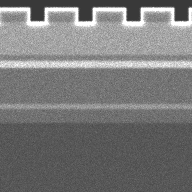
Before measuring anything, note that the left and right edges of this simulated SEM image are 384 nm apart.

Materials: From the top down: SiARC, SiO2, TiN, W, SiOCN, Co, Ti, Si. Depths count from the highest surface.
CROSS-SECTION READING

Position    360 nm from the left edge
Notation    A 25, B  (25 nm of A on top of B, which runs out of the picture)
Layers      empty 28, SiO2 66, TiN 12, W 14, SiOCN 72, Co 10, Ti 28, Si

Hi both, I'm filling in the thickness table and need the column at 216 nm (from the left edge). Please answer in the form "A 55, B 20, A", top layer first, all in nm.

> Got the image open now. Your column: SiARC 28, SiO2 66, TiN 12, W 14, SiOCN 72, Co 10, Ti 28, Si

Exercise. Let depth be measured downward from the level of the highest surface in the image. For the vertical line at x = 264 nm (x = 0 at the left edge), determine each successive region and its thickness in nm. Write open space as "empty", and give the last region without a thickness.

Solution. empty 28, SiO2 66, TiN 12, W 14, SiOCN 72, Co 10, Ti 28, Si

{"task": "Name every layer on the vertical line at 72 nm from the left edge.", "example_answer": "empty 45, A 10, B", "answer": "empty 28, SiO2 66, TiN 12, W 14, SiOCN 72, Co 10, Ti 28, Si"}